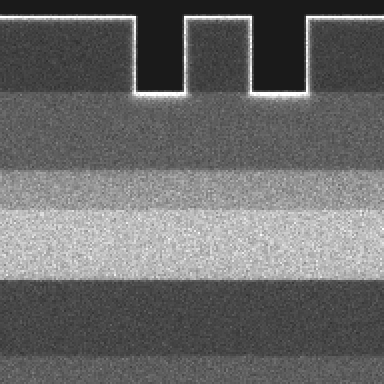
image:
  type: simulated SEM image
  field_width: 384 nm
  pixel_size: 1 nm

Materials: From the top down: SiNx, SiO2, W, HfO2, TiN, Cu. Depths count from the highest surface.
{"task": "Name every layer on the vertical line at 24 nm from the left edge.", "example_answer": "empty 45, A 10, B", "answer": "SiNx 76, SiO2 78, W 40, HfO2 70, TiN 76, Cu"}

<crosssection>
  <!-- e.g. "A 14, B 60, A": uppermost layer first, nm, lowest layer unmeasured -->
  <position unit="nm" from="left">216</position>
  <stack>SiNx 76, SiO2 78, W 40, HfO2 70, TiN 76, Cu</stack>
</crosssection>